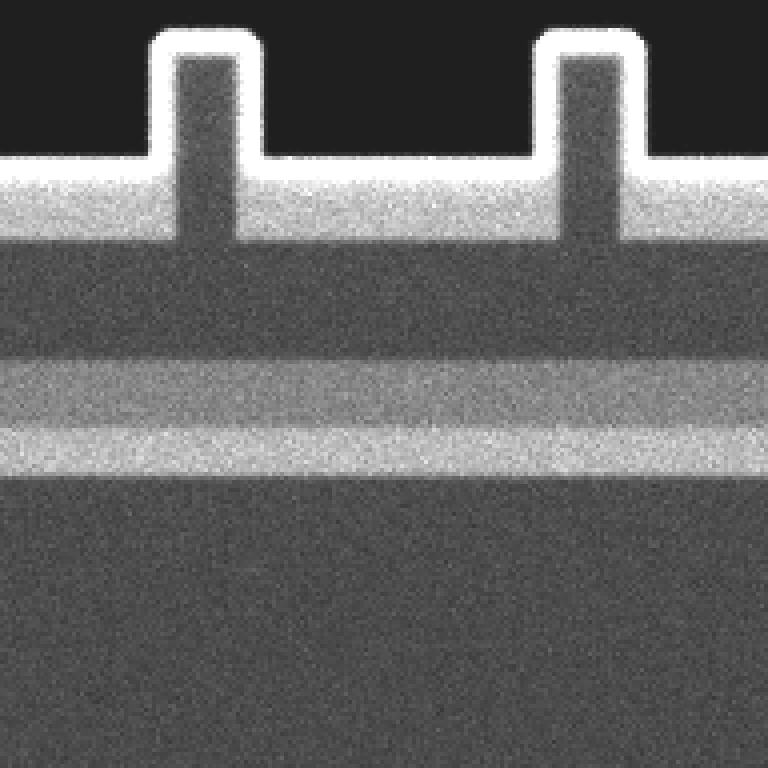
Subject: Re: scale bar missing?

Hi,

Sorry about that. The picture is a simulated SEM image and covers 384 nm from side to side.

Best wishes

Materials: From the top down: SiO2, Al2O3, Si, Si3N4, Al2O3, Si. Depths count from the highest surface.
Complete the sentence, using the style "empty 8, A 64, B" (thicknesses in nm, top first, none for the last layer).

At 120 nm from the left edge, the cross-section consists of SiO2 76, Al2O3 28, Si 60, Si3N4 34, Al2O3 24, Si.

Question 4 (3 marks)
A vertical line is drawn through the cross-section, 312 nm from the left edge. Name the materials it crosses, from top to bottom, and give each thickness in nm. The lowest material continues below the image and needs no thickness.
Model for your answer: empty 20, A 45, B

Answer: SiO2 76, Al2O3 28, Si 60, Si3N4 34, Al2O3 24, Si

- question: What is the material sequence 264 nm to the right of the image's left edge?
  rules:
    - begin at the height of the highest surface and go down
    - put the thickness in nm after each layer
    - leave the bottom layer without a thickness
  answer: empty 64, SiO2 12, Al2O3 28, Si 60, Si3N4 34, Al2O3 24, Si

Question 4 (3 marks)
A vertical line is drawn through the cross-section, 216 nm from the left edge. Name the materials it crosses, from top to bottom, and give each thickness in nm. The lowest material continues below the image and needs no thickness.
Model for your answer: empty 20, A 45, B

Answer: empty 64, SiO2 12, Al2O3 28, Si 60, Si3N4 34, Al2O3 24, Si